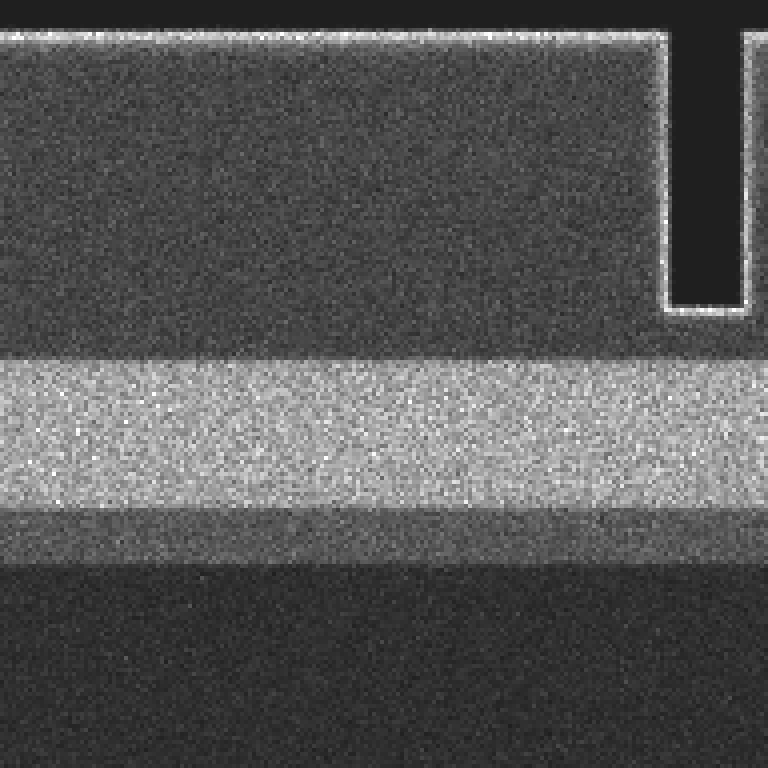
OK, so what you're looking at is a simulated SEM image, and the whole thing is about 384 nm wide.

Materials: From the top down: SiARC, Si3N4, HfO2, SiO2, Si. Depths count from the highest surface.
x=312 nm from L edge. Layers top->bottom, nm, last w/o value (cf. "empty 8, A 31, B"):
SiARC 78, Si3N4 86, HfO2 74, SiO2 28, Si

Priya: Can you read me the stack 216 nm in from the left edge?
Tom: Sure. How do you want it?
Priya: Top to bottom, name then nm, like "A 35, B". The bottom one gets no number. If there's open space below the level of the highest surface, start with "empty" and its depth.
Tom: SiARC 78, Si3N4 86, HfO2 74, SiO2 28, Si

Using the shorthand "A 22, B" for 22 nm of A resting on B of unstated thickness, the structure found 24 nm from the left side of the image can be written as SiARC 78, Si3N4 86, HfO2 74, SiO2 28, Si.